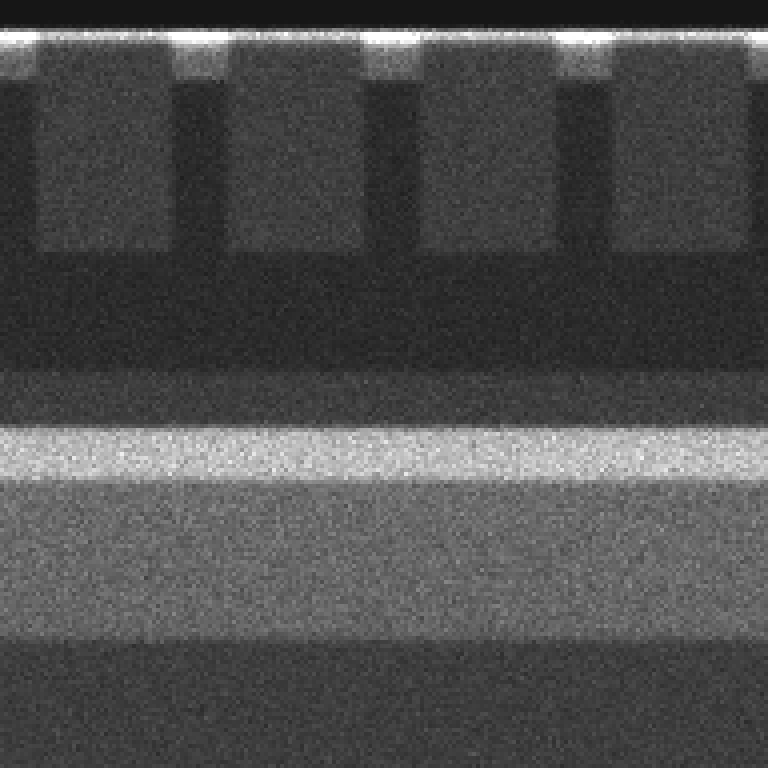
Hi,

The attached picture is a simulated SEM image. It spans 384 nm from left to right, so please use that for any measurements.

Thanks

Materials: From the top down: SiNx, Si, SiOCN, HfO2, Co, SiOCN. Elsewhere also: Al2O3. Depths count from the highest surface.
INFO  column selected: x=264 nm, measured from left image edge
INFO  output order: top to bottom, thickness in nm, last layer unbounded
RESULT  SiNx 110, Si 60, SiOCN 28, HfO2 26, Co 80, SiOCN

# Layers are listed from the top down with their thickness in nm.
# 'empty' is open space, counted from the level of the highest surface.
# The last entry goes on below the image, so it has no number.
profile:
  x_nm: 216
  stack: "SiNx 110, Si 60, SiOCN 28, HfO2 26, Co 80, SiOCN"